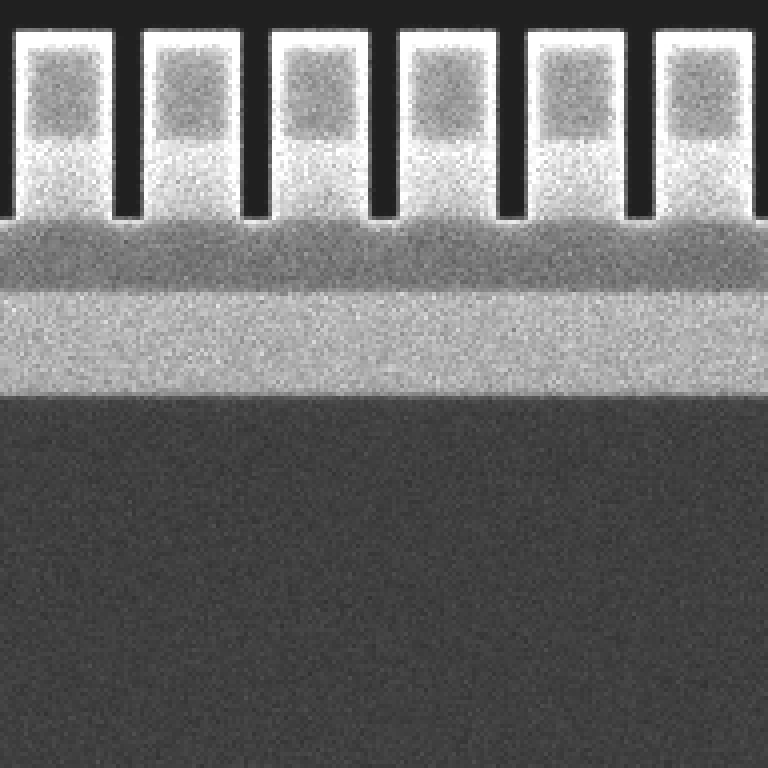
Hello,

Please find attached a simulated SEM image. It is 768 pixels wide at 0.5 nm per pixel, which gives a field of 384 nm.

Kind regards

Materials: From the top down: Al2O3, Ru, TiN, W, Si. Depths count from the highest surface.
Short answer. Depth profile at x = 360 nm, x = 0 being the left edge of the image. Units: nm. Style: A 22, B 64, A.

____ Al2O3 54, Ru 40, TiN 36, W 52, Si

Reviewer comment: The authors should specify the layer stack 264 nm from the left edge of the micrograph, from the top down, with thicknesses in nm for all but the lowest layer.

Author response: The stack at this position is Al2O3 54, Ru 40, TiN 36, W 52, Si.